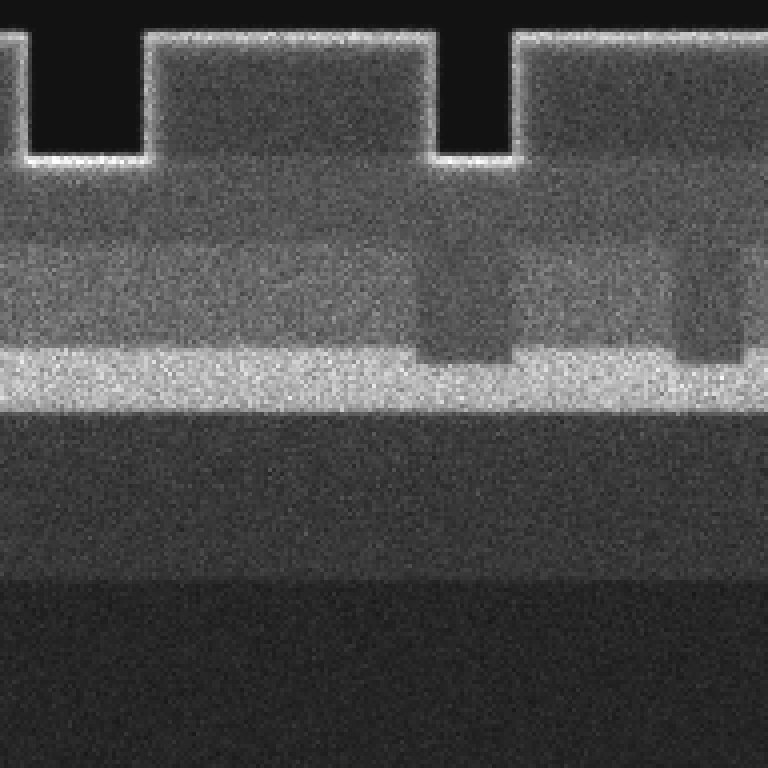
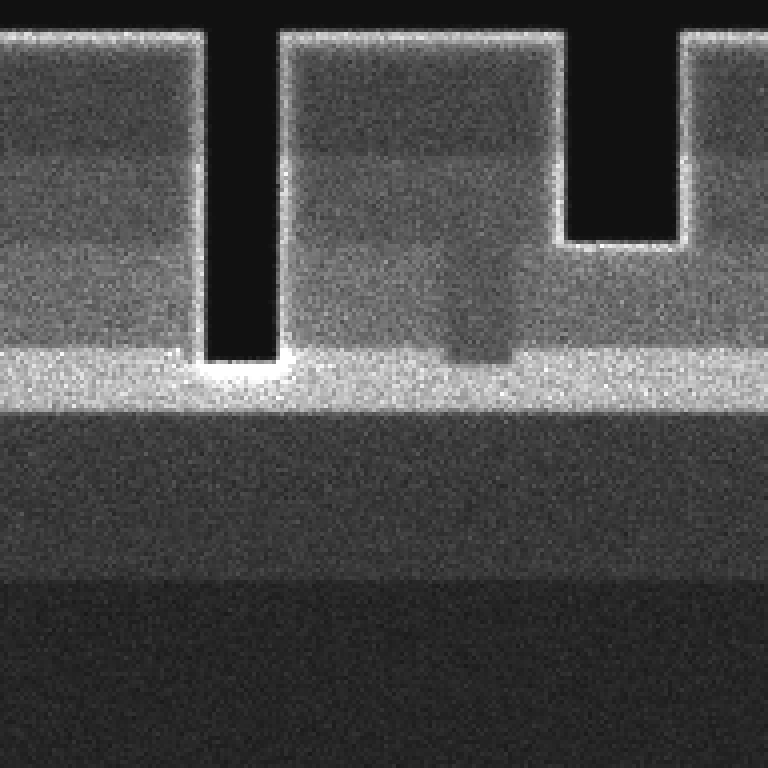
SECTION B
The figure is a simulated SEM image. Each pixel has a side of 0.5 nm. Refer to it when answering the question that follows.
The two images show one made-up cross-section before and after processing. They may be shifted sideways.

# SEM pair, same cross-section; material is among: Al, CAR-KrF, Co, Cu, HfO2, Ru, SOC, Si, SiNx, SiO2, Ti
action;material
removed;SiO2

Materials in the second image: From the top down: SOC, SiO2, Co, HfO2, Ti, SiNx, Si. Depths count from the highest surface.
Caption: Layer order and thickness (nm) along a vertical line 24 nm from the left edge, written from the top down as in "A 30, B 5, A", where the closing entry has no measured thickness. SOC 62, SiO2 44, Co 52, HfO2 32, Ti 42, SiNx 42, Si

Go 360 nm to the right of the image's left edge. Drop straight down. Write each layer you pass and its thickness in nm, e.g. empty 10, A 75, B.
SOC 62, SiO2 44, Co 52, HfO2 32, Ti 42, SiNx 42, Si